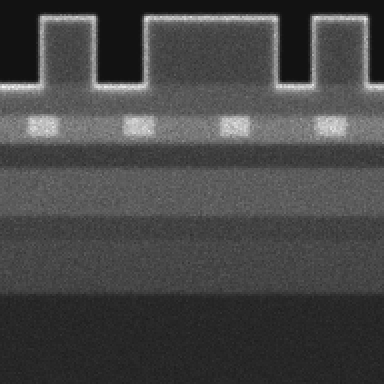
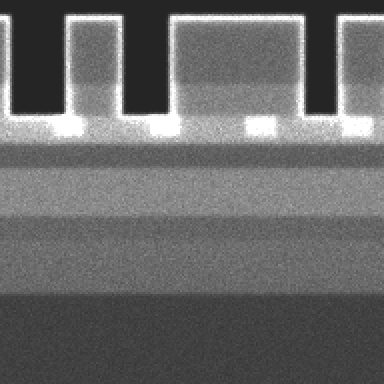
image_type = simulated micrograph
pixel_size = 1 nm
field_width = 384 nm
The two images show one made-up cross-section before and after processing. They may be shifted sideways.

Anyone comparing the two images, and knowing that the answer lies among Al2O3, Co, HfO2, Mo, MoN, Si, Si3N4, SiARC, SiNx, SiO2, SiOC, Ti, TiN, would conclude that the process removed SiO2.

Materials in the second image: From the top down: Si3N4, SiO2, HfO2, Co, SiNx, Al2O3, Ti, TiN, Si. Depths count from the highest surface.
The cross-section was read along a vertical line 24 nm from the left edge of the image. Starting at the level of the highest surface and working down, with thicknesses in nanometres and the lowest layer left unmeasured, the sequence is empty 100, Co 28, SiNx 24, Al2O3 48, Ti 24, TiN 54, Si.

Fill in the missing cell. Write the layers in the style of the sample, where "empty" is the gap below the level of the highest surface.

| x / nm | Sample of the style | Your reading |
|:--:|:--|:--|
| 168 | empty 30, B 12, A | empty 100, HfO2 20, Co 8, SiNx 24, Al2O3 48, Ti 24, TiN 54, Si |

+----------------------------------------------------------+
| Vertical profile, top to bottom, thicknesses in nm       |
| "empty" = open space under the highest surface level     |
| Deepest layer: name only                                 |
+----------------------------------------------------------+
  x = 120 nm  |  Si3N4 68, SiO2 32, Co 28, SiNx 24, Al2O3 48, Ti 24, TiN 54, Si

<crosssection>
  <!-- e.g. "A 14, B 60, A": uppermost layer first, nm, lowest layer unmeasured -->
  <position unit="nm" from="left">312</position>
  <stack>empty 100, Co 28, SiNx 24, Al2O3 48, Ti 24, TiN 54, Si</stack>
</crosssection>